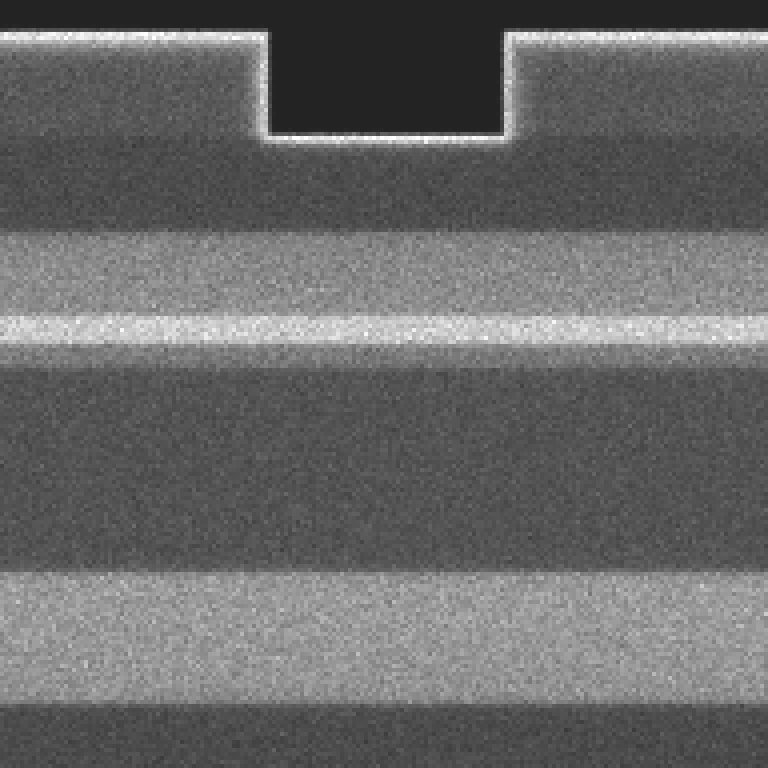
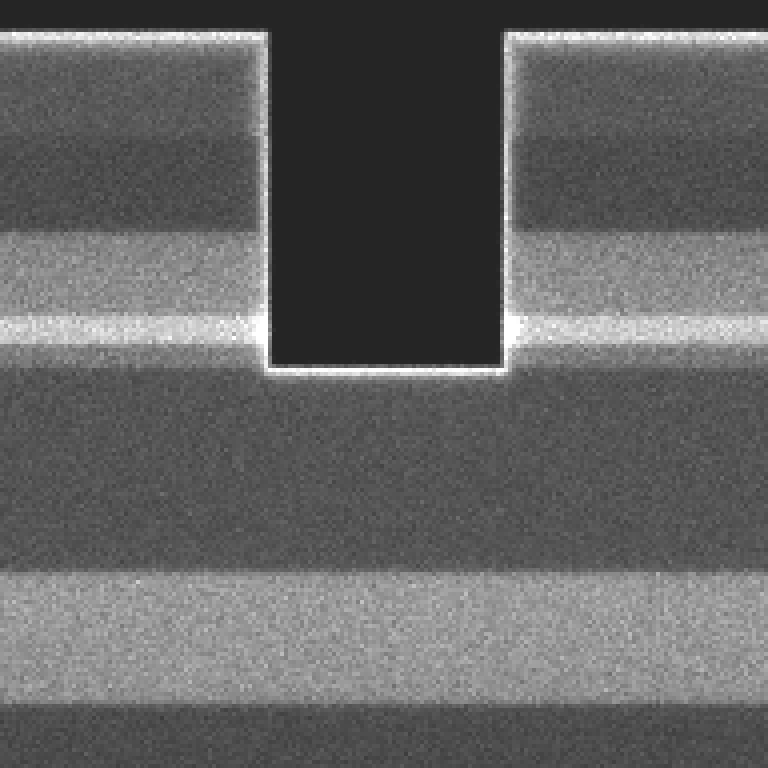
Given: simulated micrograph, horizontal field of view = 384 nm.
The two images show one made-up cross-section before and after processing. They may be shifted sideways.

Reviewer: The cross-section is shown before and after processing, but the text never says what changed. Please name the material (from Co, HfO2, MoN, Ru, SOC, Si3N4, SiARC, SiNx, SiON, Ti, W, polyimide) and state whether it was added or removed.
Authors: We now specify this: Co and HfO2 and Ru and SiNx, removed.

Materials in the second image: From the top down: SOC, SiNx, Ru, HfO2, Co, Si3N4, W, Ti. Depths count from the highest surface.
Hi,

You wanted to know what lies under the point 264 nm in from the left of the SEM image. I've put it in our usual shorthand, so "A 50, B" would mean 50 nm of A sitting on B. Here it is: SOC 52, SiNx 48, Ru 42, HfO2 14, Co 12, Si3N4 102, W 66, Ti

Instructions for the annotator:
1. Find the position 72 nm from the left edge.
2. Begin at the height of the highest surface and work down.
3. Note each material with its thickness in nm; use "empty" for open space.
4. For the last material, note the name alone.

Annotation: SOC 52, SiNx 48, Ru 42, HfO2 14, Co 12, Si3N4 102, W 66, Ti